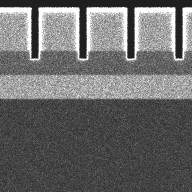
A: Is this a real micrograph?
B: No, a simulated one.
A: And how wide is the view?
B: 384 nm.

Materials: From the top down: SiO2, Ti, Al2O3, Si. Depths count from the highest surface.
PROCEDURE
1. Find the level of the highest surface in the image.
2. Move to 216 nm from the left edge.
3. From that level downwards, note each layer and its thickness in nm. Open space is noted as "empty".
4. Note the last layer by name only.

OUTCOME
SiO2 86, Ti 48, Al2O3 48, Si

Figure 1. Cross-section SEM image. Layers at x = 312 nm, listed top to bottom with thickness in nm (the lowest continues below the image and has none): SiO2 86, Ti 48, Al2O3 48, Si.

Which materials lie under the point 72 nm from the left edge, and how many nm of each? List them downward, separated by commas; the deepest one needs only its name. empty 102, Ti 32, Al2O3 48, Si